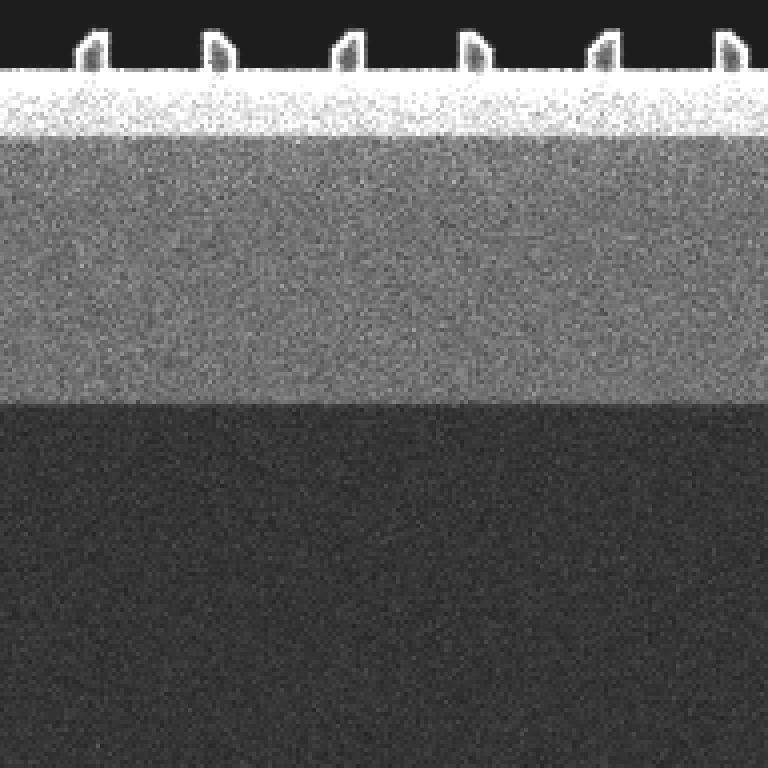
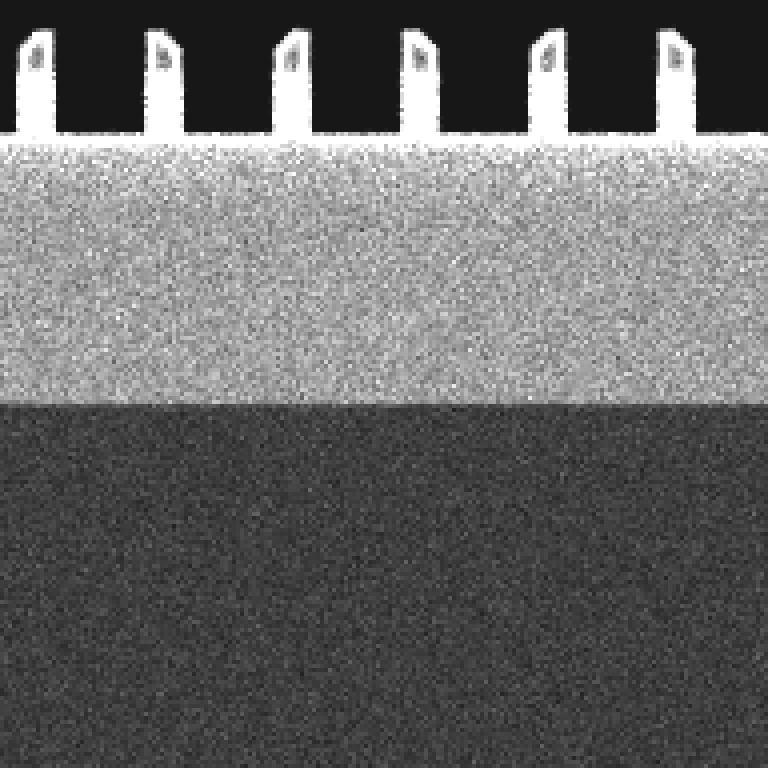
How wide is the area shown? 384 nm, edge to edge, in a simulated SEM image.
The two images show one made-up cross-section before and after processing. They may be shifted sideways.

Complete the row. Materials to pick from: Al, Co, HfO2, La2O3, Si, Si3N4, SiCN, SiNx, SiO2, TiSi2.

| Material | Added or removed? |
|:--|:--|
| HfO2 | removed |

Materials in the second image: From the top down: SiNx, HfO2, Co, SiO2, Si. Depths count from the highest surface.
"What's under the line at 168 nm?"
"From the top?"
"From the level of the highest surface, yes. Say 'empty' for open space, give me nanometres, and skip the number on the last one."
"empty 52, Co 32, SiO2 102, Si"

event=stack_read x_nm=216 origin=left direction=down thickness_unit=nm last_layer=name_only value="empty 8, SiNx 12, HfO2 32, Co 32, SiO2 102, Si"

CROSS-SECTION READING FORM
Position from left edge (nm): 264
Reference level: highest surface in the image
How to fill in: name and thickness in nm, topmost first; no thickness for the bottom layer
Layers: empty 52, Co 32, SiO2 102, Si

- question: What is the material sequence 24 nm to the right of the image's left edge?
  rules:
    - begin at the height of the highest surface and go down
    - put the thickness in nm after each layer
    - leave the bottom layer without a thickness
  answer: SiNx 20, HfO2 32, Co 32, SiO2 102, Si